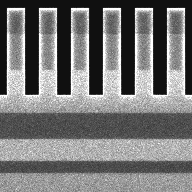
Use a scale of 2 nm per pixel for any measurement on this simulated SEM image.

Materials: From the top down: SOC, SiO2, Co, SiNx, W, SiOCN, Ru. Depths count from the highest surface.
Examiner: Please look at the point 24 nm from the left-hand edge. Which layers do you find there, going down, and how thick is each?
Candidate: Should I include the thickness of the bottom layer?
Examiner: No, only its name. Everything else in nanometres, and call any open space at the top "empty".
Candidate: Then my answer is SOC 52, SiO2 72, Co 86, SiNx 52, W 44, SiOCN 24, Ru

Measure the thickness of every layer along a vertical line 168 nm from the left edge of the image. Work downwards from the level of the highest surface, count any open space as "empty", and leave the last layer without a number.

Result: SOC 52, SiO2 72, Co 86, SiNx 52, W 44, SiOCN 24, Ru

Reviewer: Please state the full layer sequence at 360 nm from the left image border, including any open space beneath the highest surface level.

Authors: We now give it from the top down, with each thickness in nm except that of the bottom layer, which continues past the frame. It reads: SOC 52, SiO2 72, Co 86, SiNx 52, W 44, SiOCN 24, Ru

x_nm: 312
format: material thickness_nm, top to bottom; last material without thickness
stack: empty 174, Co 36, SiNx 52, W 44, SiOCN 24, Ru